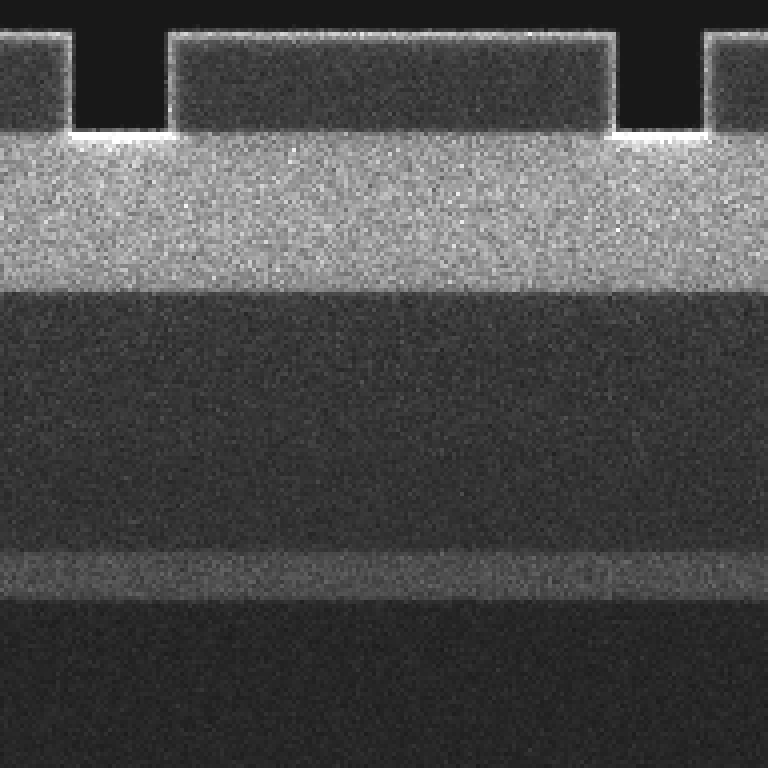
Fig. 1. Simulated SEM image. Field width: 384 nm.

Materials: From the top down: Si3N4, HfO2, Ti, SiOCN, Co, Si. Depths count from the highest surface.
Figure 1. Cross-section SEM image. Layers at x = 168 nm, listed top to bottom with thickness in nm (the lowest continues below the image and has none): Si3N4 50, HfO2 80, Ti 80, SiOCN 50, Co 24, Si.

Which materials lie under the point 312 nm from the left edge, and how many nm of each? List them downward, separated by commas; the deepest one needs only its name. empty 50, HfO2 80, Ti 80, SiOCN 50, Co 24, Si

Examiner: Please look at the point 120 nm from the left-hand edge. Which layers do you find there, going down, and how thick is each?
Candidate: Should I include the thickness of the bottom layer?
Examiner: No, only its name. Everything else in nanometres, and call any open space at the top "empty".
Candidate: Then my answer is Si3N4 50, HfO2 80, Ti 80, SiOCN 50, Co 24, Si